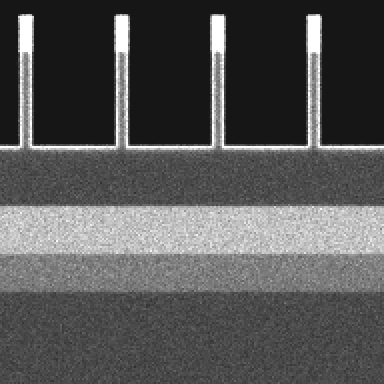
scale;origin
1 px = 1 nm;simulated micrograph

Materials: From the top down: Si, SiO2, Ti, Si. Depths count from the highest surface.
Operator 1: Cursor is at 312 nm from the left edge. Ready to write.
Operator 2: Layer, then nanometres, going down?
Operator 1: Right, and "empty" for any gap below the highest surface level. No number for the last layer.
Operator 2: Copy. Si 190, SiO2 48, Ti 38, Si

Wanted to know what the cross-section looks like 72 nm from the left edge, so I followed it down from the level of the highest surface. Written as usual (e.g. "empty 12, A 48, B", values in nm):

empty 130, Si 60, SiO2 48, Ti 38, Si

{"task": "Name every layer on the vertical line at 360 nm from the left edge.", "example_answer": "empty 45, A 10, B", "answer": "empty 130, Si 60, SiO2 48, Ti 38, Si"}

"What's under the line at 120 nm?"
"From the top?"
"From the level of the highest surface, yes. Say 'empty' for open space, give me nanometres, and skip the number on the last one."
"Si 190, SiO2 48, Ti 38, Si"